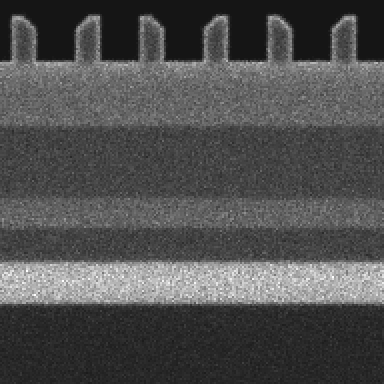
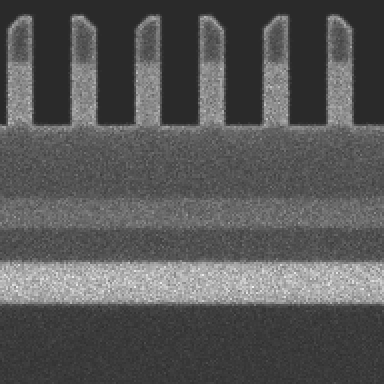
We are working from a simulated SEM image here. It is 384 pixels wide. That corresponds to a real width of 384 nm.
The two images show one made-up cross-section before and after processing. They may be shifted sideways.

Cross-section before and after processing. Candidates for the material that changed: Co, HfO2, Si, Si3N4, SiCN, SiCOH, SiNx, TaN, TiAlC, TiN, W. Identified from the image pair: W (removed).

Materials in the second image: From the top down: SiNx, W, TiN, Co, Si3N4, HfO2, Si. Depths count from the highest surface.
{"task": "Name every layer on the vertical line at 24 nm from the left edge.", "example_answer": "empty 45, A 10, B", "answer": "SiNx 46, W 64, TiN 72, Co 30, Si3N4 34, HfO2 42, Si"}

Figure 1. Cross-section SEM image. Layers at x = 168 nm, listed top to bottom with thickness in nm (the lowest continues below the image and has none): empty 110, TiN 72, Co 30, Si3N4 34, HfO2 42, Si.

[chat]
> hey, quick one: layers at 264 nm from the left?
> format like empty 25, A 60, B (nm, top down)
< empty 12, SiNx 34, W 64, TiN 72, Co 30, Si3N4 34, HfO2 42, Si